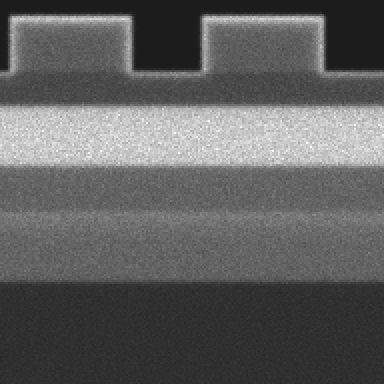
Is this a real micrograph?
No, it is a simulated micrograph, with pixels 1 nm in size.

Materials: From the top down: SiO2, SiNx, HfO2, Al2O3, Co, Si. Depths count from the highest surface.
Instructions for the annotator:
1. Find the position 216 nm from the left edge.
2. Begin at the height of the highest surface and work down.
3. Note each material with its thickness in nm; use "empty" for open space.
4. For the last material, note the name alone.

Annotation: SiO2 56, SiNx 34, HfO2 60, Al2O3 46, Co 70, Si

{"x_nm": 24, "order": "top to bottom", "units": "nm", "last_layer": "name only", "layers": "SiO2 56, SiNx 34, HfO2 60, Al2O3 46, Co 70, Si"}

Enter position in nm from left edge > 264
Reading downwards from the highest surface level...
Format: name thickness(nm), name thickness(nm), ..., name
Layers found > SiO2 56, SiNx 34, HfO2 60, Al2O3 46, Co 70, Si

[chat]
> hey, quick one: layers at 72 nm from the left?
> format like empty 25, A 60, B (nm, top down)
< SiO2 56, SiNx 34, HfO2 60, Al2O3 46, Co 70, Si